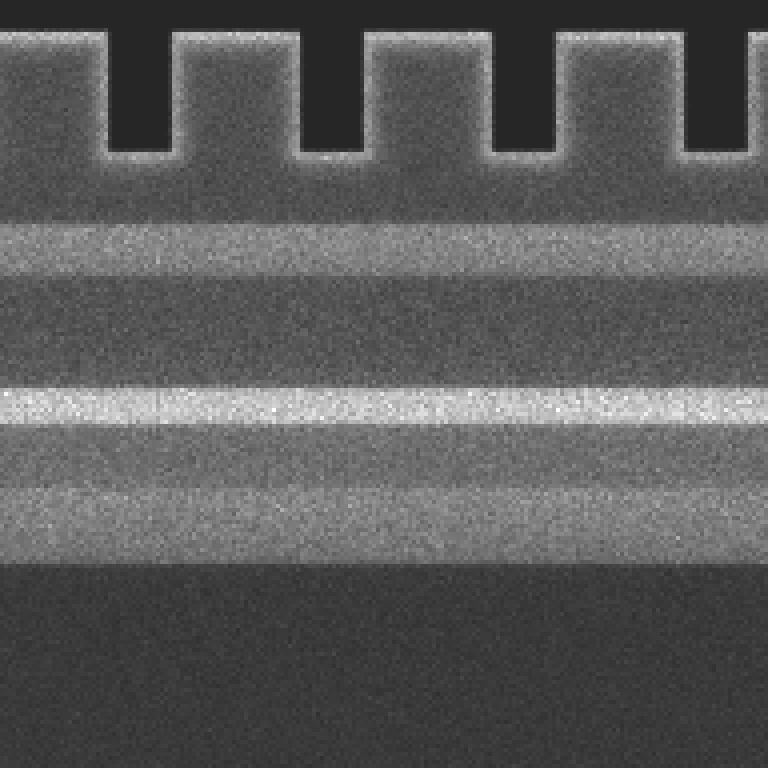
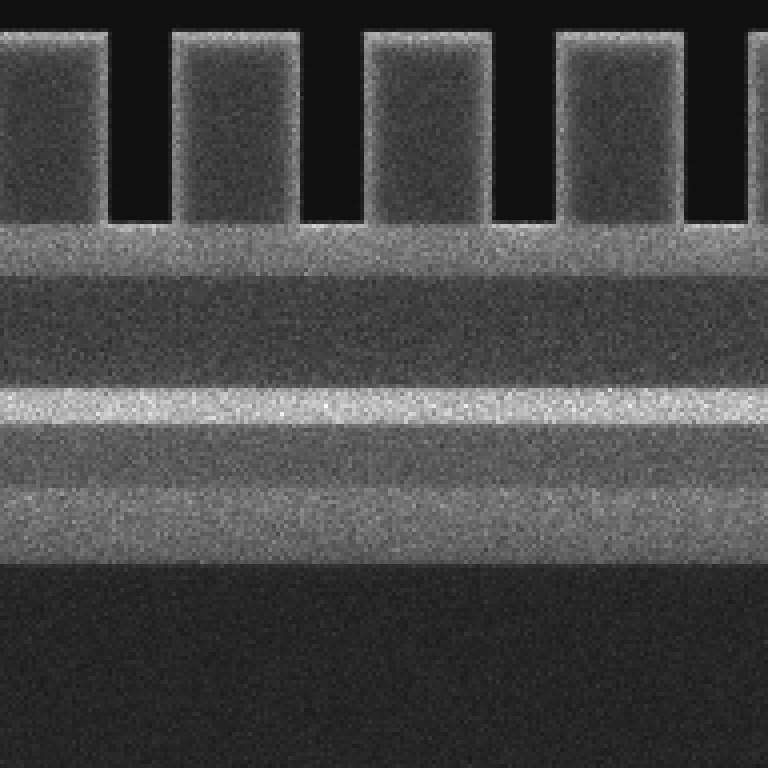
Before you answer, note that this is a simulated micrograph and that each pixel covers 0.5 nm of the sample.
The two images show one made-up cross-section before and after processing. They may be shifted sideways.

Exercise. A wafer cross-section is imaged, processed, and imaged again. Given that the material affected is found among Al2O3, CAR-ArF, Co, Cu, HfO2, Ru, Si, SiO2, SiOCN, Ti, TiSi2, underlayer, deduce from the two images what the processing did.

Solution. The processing removed underlayer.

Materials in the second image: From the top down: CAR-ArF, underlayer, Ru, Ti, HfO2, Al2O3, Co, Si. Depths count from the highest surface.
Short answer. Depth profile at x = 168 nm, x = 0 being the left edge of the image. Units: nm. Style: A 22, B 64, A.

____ empty 96, Ru 26, Ti 56, HfO2 18, Al2O3 32, Co 38, Si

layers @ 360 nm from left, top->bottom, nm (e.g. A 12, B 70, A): empty 96, Ru 26, Ti 56, HfO2 18, Al2O3 32, Co 38, Si